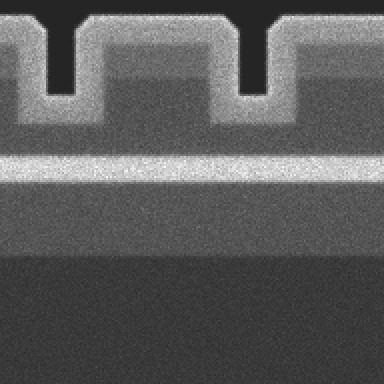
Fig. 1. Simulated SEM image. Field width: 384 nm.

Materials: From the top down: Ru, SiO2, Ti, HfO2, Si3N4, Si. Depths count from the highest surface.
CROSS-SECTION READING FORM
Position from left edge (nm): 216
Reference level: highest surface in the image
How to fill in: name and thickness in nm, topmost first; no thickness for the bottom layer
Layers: Ru 108, Ti 32, HfO2 26, Si3N4 74, Si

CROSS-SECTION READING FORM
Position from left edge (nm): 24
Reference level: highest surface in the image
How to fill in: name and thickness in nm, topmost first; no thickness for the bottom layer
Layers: Ru 108, Ti 32, HfO2 26, Si3N4 74, Si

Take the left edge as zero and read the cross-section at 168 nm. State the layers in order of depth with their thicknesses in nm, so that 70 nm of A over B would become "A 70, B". Ru 28, SiO2 34, Ti 78, HfO2 26, Si3N4 74, Si